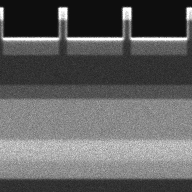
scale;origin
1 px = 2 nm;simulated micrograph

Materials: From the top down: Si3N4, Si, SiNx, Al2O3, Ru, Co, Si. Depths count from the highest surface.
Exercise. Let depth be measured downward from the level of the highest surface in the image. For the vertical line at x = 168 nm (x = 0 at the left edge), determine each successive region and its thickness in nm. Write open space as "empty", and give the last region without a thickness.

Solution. empty 60, Si3N4 34, Si 60, SiNx 28, Al2O3 82, Ru 42, Co 36, Si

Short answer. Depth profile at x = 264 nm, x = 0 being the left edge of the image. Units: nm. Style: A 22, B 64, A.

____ empty 60, Si3N4 34, Si 60, SiNx 28, Al2O3 82, Ru 42, Co 36, Si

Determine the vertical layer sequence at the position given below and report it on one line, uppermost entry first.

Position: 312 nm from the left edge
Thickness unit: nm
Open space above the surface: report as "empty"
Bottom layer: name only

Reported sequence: empty 60, Si3N4 34, Si 60, SiNx 28, Al2O3 82, Ru 42, Co 36, Si